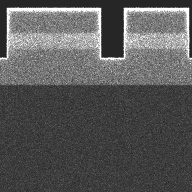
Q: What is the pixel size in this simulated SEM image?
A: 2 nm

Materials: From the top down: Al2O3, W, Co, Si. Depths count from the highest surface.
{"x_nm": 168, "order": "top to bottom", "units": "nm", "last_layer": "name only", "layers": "Al2O3 50, W 32, Co 72, Si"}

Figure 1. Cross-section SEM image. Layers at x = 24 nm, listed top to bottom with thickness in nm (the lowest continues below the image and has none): Al2O3 50, W 32, Co 72, Si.